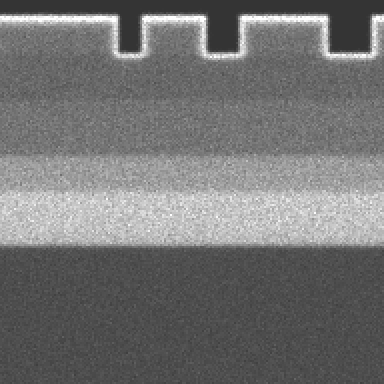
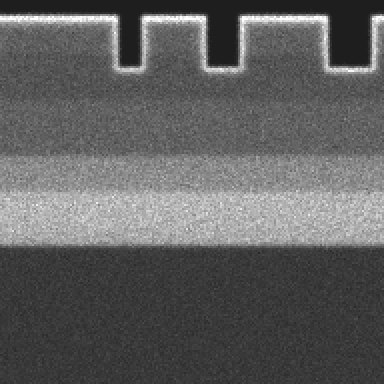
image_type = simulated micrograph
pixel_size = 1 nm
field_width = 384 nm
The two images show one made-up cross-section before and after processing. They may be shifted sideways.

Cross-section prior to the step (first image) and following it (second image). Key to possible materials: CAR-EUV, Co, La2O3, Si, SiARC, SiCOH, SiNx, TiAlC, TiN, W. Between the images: SiNx was removed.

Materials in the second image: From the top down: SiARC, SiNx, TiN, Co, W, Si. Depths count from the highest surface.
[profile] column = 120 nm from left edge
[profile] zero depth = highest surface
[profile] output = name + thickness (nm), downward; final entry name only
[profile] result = empty 52, SiNx 32, TiN 56, Co 36, W 54, Si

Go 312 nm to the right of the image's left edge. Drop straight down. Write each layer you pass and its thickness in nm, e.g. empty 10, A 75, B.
SiARC 38, SiNx 46, TiN 56, Co 36, W 54, Si